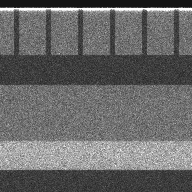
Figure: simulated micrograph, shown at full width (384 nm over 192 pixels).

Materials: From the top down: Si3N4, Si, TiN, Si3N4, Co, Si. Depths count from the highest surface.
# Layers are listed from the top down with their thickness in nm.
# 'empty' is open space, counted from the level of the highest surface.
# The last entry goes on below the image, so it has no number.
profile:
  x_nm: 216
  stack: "Si3N4 94, Si 60, TiN 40, Si3N4 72, Co 58, Si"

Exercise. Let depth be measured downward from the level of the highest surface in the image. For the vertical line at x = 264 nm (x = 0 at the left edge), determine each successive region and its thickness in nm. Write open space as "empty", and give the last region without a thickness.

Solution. Si3N4 94, Si 60, TiN 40, Si3N4 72, Co 58, Si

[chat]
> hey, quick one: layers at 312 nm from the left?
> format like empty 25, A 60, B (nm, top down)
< Si3N4 94, Si 60, TiN 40, Si3N4 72, Co 58, Si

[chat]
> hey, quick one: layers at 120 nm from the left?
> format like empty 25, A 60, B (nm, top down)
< Si3N4 94, Si 60, TiN 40, Si3N4 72, Co 58, Si